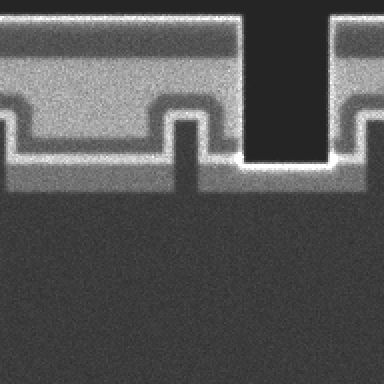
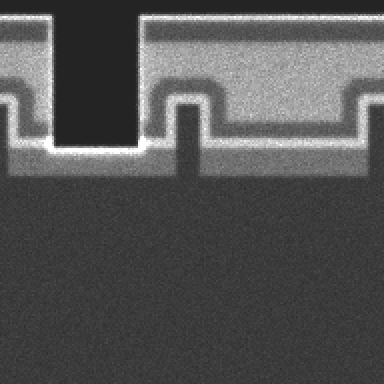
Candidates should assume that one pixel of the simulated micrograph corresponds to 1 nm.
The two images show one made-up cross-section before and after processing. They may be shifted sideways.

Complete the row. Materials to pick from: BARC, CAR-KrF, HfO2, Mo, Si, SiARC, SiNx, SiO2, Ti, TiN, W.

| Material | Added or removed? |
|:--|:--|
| SiARC | removed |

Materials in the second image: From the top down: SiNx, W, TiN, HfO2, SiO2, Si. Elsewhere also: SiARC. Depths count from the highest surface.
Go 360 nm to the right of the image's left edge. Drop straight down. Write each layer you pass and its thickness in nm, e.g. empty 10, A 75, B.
SiNx 26, W 36, TiN 18, HfO2 52, SiO2 28, Si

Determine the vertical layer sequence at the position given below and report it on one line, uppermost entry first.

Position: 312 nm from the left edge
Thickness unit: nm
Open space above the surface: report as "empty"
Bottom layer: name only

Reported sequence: SiNx 26, W 80, TiN 16, HfO2 10, SiO2 28, Si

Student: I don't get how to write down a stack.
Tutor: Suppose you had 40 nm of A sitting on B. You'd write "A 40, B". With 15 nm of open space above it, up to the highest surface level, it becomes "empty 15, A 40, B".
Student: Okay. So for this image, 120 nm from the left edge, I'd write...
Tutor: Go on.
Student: empty 132, SiO2 28, Si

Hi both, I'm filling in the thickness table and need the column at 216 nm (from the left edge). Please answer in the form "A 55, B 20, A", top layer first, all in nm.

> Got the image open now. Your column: SiNx 26, W 40, TiN 56, HfO2 10, SiO2 28, Si